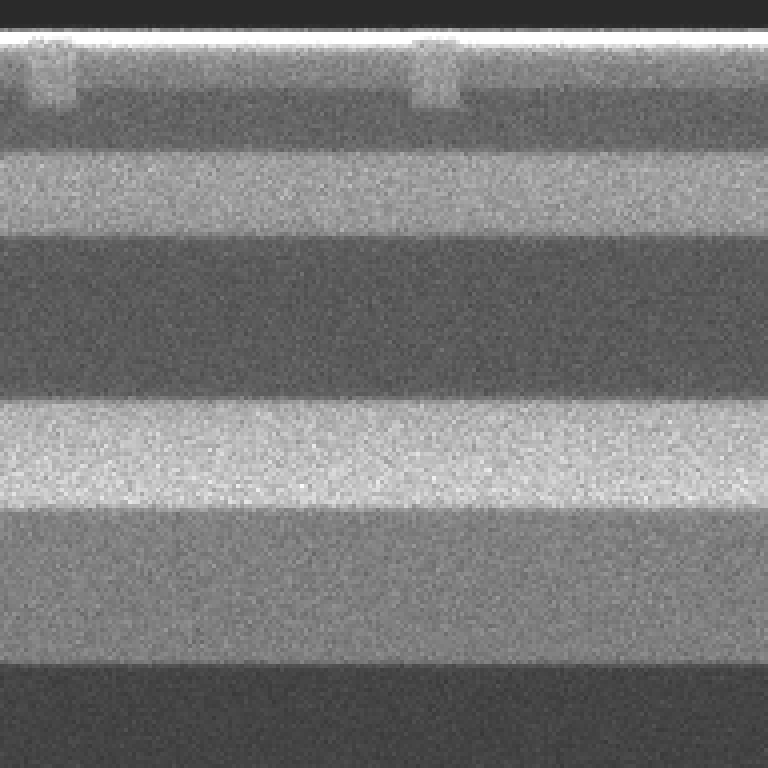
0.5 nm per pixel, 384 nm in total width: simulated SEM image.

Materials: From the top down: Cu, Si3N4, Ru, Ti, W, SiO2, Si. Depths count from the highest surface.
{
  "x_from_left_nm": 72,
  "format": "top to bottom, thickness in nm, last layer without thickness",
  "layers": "SiO2 28, Si3N4 32, Ru 42, Ti 82, W 54, SiO2 78, Si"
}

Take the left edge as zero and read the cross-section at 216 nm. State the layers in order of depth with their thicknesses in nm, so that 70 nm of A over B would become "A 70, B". Cu 38, Si3N4 22, Ru 42, Ti 82, W 54, SiO2 78, Si